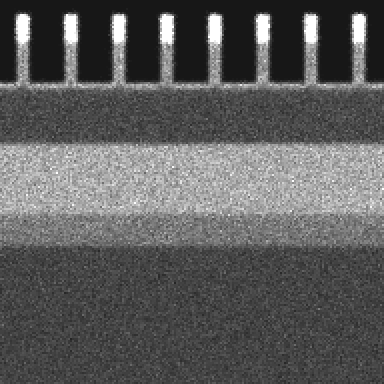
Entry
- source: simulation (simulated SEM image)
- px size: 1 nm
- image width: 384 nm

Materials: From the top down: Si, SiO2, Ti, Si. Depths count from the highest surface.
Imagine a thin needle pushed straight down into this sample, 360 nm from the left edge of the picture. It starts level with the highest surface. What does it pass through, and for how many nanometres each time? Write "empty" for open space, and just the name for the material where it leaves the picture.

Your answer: Si 128, SiO2 70, Ti 32, Si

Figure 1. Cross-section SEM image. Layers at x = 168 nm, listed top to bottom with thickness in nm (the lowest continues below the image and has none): Si 128, SiO2 70, Ti 32, Si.